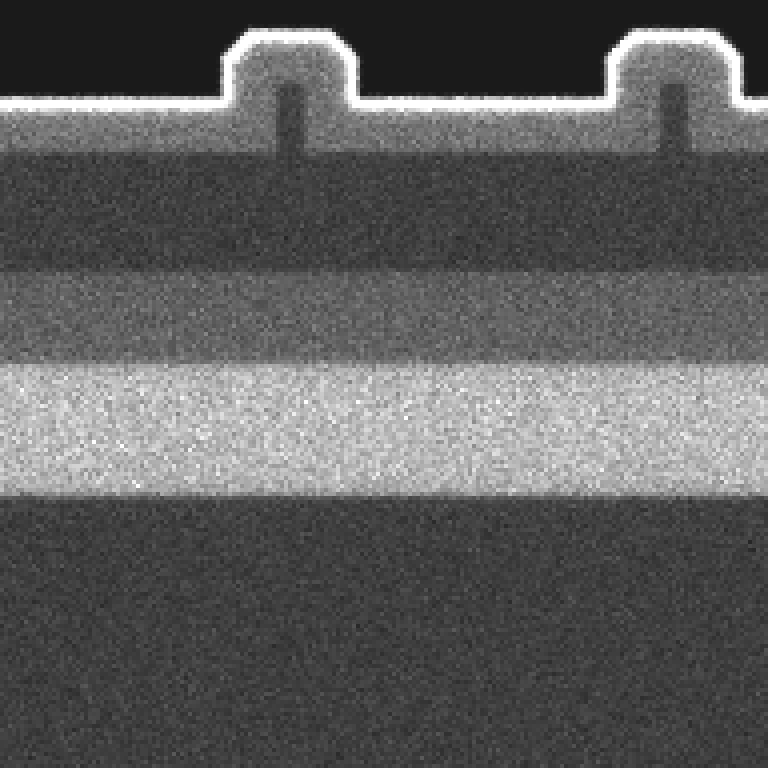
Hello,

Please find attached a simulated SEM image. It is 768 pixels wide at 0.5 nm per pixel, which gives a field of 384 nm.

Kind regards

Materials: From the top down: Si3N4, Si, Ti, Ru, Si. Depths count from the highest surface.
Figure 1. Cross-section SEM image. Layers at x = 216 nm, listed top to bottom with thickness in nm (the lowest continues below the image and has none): empty 34, Si3N4 26, Si 60, Ti 46, Ru 66, Si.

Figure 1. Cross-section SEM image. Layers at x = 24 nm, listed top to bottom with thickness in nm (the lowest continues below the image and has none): empty 34, Si3N4 26, Si 60, Ti 46, Ru 66, Si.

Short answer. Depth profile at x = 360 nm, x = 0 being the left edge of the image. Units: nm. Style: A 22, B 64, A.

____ empty 4, Si3N4 56, Si 60, Ti 46, Ru 66, Si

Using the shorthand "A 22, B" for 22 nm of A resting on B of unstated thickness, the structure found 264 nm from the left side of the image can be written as empty 34, Si3N4 26, Si 60, Ti 46, Ru 66, Si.